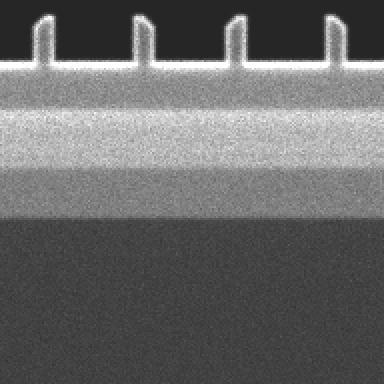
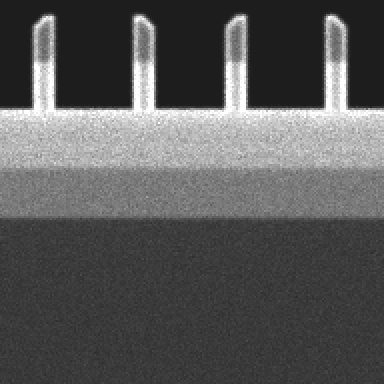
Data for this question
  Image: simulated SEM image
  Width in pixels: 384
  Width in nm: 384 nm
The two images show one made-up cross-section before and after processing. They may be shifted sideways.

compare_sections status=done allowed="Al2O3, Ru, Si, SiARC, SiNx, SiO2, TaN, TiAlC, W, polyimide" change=removed material="Al2O3"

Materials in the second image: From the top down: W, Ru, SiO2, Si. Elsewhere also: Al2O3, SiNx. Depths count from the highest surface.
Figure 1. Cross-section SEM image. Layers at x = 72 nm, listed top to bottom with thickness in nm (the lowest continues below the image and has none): empty 94, W 42, Ru 16, SiO2 50, Si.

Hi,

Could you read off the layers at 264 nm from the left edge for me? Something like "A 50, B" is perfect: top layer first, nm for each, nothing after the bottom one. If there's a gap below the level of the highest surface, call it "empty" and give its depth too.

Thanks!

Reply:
empty 94, W 42, Ru 16, SiO2 50, Si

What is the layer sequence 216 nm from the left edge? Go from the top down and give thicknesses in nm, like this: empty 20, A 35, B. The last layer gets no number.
empty 94, W 42, Ru 16, SiO2 50, Si